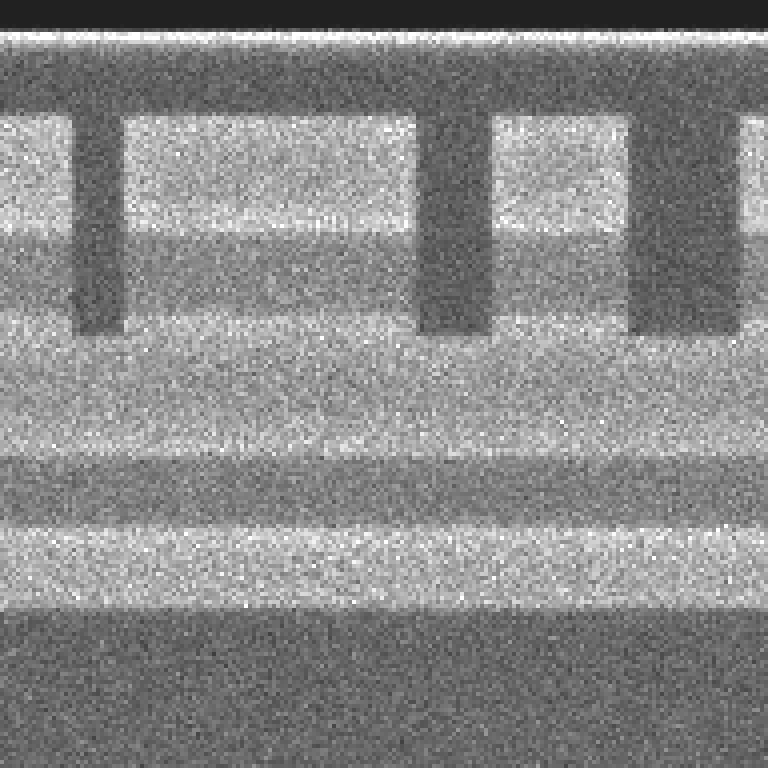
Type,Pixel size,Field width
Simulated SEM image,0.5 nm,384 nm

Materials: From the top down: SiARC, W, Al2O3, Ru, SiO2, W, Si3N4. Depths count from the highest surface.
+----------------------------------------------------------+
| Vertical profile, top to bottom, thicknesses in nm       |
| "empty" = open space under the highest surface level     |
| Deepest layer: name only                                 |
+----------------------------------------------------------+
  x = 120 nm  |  SiARC 42, W 58, Al2O3 42, Ru 70, SiO2 36, W 40, Si3N4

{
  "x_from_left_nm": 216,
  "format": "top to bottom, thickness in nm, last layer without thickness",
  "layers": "SiARC 152, Ru 60, SiO2 36, W 40, Si3N4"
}